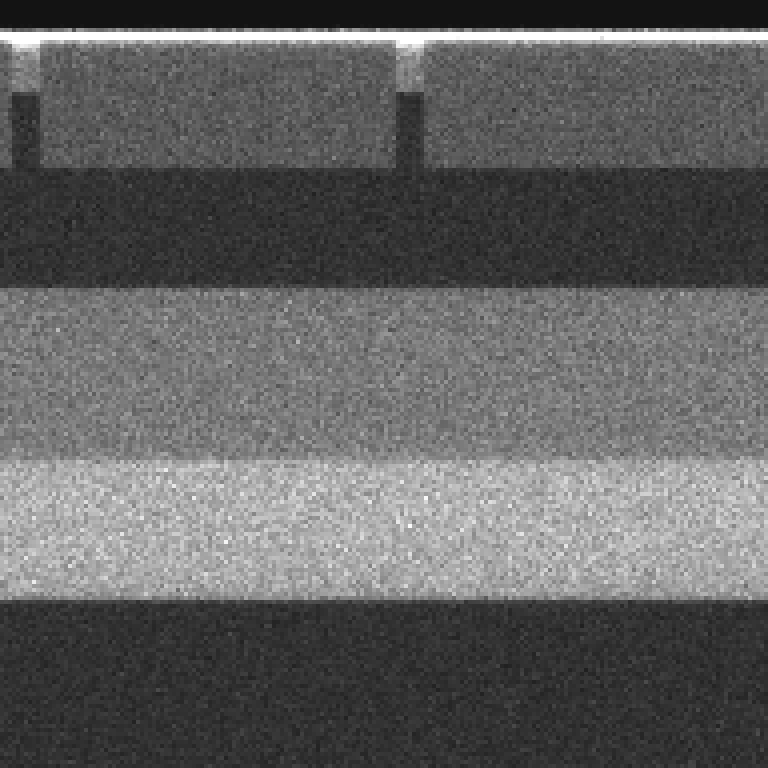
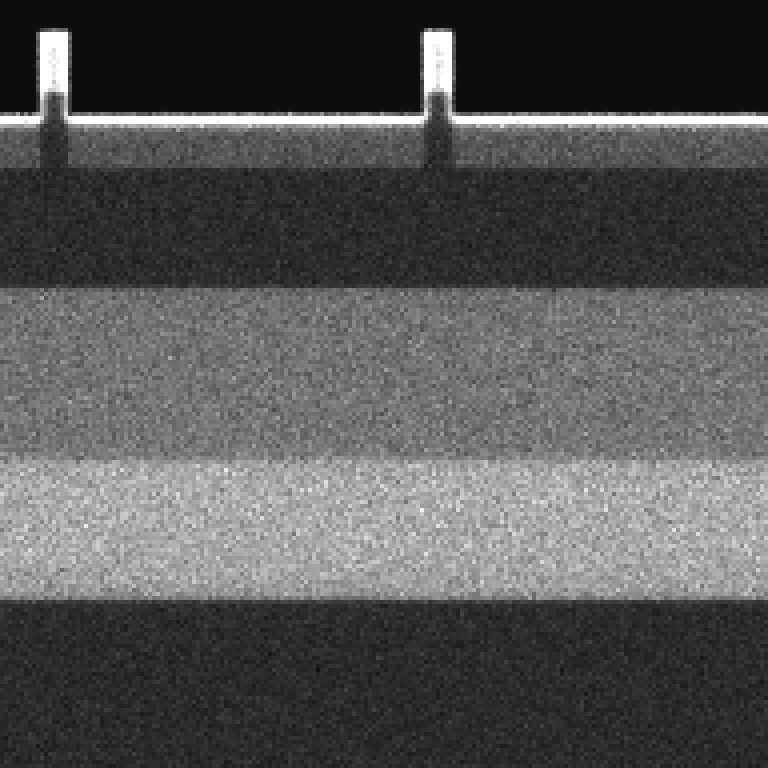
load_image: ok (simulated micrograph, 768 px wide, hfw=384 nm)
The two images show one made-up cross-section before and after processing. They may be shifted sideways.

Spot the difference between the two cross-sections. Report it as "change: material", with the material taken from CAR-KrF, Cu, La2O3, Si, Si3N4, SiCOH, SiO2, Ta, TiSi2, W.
removed: Si3N4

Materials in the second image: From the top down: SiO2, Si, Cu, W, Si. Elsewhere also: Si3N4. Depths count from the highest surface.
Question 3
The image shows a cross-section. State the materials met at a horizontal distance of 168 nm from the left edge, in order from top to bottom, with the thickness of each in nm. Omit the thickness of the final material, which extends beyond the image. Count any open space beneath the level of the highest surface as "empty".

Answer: empty 42, Si3N4 26, Si 60, Cu 86, W 70, Si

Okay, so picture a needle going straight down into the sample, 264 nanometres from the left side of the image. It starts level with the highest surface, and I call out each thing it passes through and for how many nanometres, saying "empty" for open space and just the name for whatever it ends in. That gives empty 42, Si3N4 26, Si 60, Cu 86, W 70, Si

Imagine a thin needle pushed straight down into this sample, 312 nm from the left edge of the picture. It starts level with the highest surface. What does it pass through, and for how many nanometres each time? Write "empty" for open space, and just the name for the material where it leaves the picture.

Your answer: empty 42, Si3N4 26, Si 60, Cu 86, W 70, Si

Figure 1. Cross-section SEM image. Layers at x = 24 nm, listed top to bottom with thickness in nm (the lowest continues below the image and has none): SiO2 30, Si 98, Cu 86, W 70, Si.